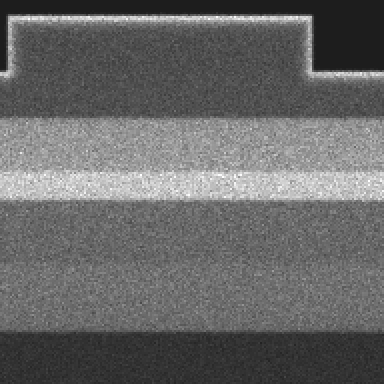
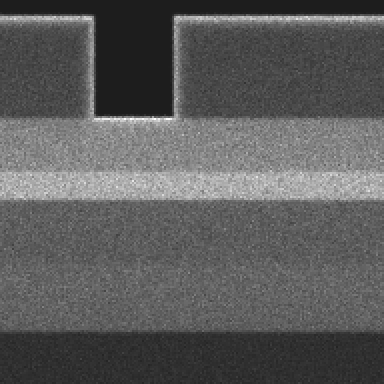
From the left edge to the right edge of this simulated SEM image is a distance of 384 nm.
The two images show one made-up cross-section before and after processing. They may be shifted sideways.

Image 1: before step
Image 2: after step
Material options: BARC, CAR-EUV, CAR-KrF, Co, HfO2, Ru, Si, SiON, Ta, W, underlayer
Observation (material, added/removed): underlayer, removed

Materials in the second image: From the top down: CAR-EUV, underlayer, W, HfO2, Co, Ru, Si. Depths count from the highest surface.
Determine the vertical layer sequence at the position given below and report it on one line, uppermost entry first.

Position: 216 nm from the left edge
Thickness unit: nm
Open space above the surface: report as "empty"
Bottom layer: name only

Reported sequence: CAR-EUV 56, underlayer 46, W 54, HfO2 28, Co 64, Ru 68, Si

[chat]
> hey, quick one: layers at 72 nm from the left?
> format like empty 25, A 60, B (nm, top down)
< CAR-EUV 56, underlayer 46, W 54, HfO2 28, Co 64, Ru 68, Si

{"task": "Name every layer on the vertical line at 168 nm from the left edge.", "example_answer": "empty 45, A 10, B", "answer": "empty 102, W 54, HfO2 28, Co 64, Ru 68, Si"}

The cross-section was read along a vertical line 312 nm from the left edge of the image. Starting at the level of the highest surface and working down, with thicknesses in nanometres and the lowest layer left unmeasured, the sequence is CAR-EUV 56, underlayer 46, W 54, HfO2 28, Co 64, Ru 68, Si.